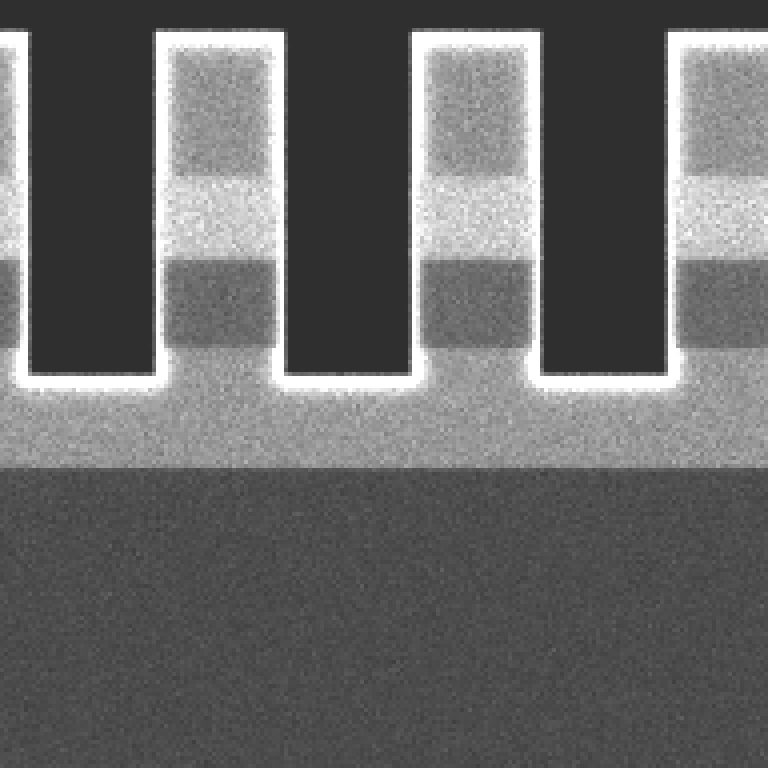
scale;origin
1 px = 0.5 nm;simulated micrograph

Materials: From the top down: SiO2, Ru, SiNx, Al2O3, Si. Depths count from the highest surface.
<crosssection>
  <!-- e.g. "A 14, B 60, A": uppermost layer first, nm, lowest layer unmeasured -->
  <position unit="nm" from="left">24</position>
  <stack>empty 172, Al2O3 46, Si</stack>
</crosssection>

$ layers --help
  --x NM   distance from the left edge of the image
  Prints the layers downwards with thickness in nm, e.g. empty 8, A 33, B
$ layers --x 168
empty 172, Al2O3 46, Si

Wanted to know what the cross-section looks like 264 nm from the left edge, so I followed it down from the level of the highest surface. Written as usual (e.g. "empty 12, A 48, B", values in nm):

SiO2 72, Ru 42, SiNx 44, Al2O3 60, Si